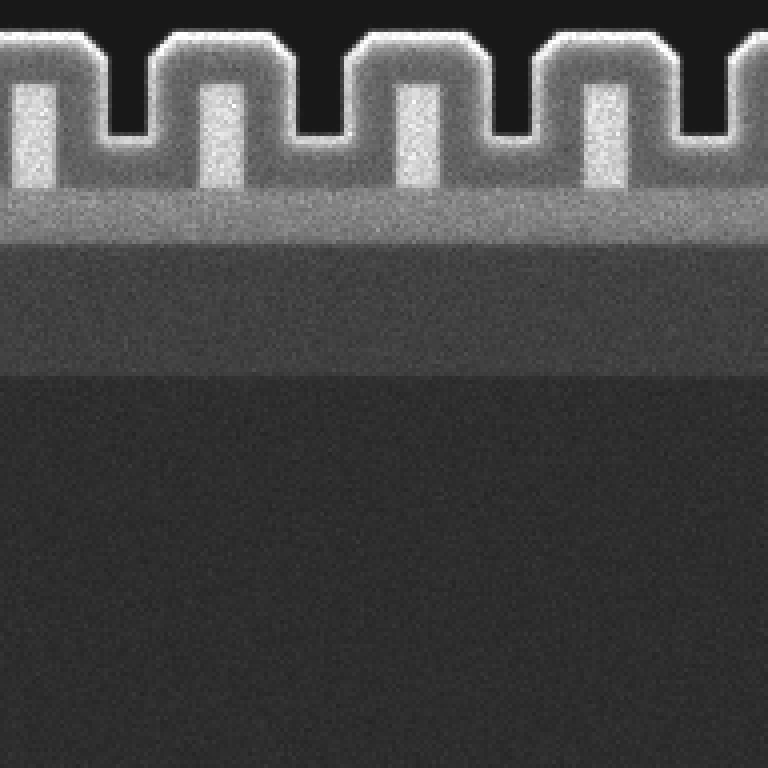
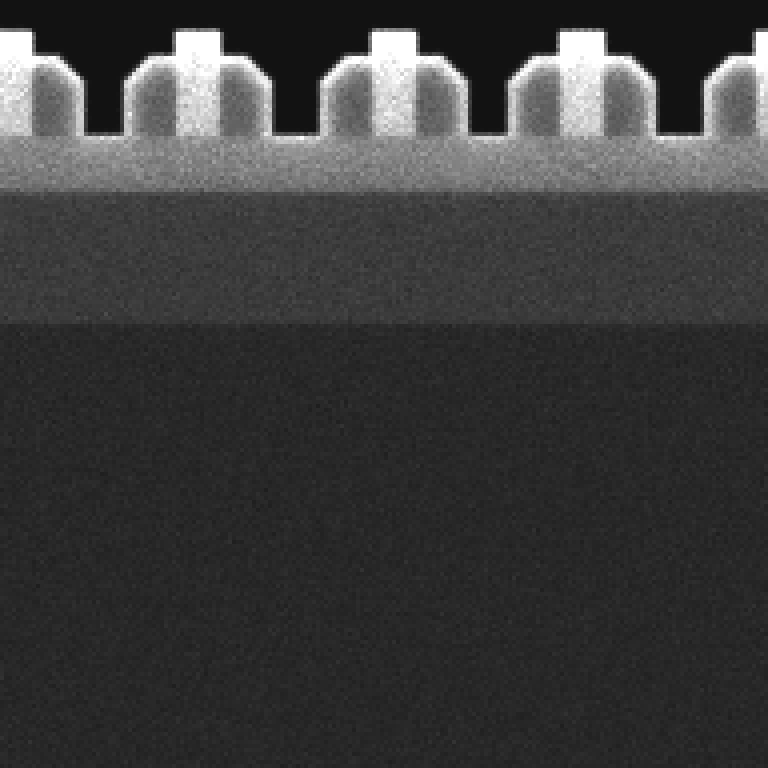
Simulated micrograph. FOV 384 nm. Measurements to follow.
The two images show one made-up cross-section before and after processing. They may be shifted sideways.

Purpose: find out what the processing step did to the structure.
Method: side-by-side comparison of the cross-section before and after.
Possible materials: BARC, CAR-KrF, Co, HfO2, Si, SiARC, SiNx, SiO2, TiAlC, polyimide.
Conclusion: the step removed SiO2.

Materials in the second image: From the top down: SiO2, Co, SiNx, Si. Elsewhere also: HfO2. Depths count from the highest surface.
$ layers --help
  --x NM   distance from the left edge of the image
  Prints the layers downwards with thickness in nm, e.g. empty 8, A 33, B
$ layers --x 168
empty 16, SiO2 36, Co 28, SiNx 66, Si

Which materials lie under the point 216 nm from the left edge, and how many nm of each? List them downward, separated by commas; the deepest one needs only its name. empty 12, SiO2 40, Co 28, SiNx 66, Si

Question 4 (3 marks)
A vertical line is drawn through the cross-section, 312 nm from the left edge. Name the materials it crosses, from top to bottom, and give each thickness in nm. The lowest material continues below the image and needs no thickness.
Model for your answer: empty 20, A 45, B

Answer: empty 12, SiO2 40, Co 28, SiNx 66, Si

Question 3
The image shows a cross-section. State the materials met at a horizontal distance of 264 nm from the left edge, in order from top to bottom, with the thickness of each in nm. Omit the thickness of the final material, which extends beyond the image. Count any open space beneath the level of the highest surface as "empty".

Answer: empty 14, SiO2 38, Co 28, SiNx 66, Si